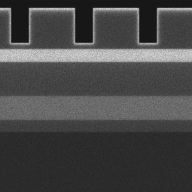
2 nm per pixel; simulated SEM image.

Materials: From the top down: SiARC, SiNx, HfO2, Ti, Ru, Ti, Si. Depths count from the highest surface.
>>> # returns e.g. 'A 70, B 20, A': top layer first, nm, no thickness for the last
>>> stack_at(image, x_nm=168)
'empty 70, SiNx 12, HfO2 26, Ti 68, Ru 48, Ti 24, Si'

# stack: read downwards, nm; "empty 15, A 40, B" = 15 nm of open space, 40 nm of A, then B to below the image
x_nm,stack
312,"empty 70, SiNx 12, HfO2 26, Ti 68, Ru 48, Ti 24, Si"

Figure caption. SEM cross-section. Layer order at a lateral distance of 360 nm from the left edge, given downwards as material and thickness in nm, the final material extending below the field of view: SiARC 12, SiNx 70, HfO2 26, Ti 68, Ru 48, Ti 24, Si